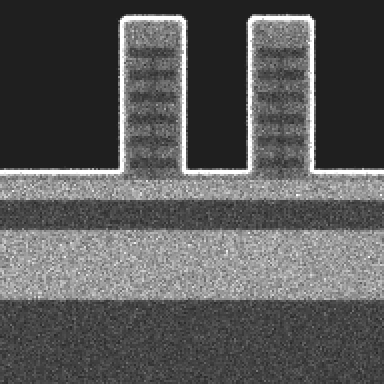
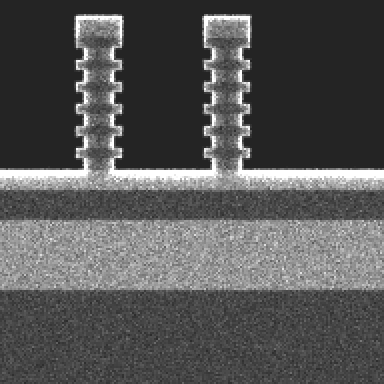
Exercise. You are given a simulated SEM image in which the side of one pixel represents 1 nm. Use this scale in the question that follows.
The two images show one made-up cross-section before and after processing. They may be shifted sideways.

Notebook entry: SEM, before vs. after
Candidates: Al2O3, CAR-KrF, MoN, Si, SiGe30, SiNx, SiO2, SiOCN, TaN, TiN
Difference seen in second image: SiNx removed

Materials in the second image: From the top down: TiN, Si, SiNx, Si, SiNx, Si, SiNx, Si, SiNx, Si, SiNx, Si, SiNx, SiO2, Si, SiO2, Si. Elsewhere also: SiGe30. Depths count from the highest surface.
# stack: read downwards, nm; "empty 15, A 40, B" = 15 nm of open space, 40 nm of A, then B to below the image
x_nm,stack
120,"TiN 22, Si 10, empty 12, Si 10, empty 12, Si 10, empty 12, Si 10, empty 12, Si 10, empty 12, Si 10, empty 12, SiO2 20, Si 30, SiO2 70, Si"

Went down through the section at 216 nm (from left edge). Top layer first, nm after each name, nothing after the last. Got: TiN 22, Si 10, SiNx 12, Si 10, SiNx 12, Si 10, SiNx 12, Si 10, SiNx 12, Si 10, SiNx 12, Si 10, SiNx 12, SiO2 20, Si 30, SiO2 70, Si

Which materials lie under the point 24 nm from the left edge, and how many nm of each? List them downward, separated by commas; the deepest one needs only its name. empty 154, SiO2 20, Si 30, SiO2 70, Si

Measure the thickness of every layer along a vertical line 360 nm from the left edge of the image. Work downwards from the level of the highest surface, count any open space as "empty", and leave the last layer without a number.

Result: empty 154, SiO2 20, Si 30, SiO2 70, Si